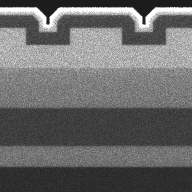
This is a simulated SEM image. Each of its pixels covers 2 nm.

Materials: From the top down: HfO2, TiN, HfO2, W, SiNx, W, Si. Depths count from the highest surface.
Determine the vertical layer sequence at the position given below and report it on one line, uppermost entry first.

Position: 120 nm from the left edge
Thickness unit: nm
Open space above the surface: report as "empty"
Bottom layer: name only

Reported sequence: HfO2 20, TiN 54, HfO2 46, W 80, SiNx 76, W 42, Si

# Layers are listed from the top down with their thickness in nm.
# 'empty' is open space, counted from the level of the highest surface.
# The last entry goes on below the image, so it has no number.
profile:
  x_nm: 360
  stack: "HfO2 14, TiN 26, HfO2 80, W 80, SiNx 76, W 42, Si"